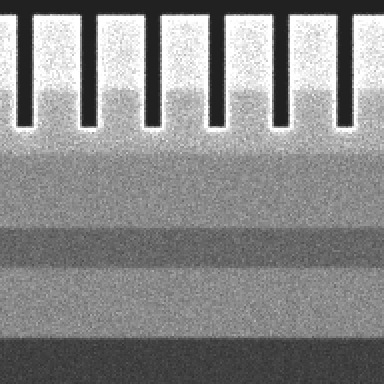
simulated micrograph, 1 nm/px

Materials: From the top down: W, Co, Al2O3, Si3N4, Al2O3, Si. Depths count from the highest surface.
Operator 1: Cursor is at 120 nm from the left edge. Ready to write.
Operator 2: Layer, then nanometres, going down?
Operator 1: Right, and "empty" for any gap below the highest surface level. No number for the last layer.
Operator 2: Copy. W 74, Co 64, Al2O3 74, Si3N4 40, Al2O3 70, Si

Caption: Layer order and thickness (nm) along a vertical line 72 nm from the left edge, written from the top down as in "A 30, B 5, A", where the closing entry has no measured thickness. W 74, Co 64, Al2O3 74, Si3N4 40, Al2O3 70, Si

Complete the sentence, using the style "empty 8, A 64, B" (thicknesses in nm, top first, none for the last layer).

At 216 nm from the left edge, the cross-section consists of empty 112, Co 26, Al2O3 74, Si3N4 40, Al2O3 70, Si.